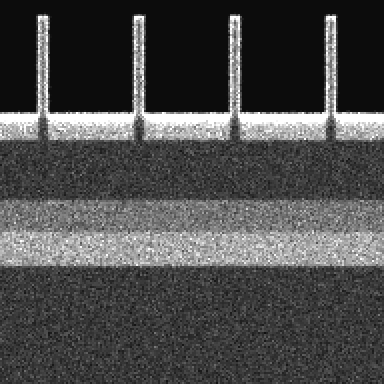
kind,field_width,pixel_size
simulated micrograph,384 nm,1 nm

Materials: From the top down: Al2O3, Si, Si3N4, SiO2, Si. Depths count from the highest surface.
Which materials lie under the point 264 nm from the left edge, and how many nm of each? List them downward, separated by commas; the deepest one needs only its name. empty 98, Al2O3 26, Si 60, Si3N4 32, SiO2 34, Si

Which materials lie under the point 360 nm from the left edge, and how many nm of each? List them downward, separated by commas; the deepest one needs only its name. empty 98, Al2O3 26, Si 60, Si3N4 32, SiO2 34, Si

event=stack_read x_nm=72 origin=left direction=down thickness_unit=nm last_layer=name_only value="empty 98, Al2O3 26, Si 60, Si3N4 32, SiO2 34, Si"